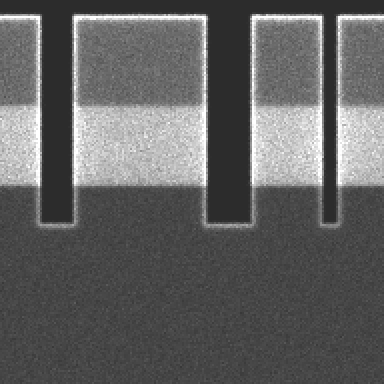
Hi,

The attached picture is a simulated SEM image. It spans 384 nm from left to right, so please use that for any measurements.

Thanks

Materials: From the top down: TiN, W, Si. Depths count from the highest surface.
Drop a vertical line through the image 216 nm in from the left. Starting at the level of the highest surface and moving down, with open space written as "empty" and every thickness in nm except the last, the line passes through empty 208, Si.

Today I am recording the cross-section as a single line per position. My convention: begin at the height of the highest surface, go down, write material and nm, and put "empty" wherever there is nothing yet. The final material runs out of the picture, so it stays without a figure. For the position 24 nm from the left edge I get TiN 90, W 80, Si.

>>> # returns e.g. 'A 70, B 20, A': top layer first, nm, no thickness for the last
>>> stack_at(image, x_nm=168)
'TiN 90, W 80, Si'